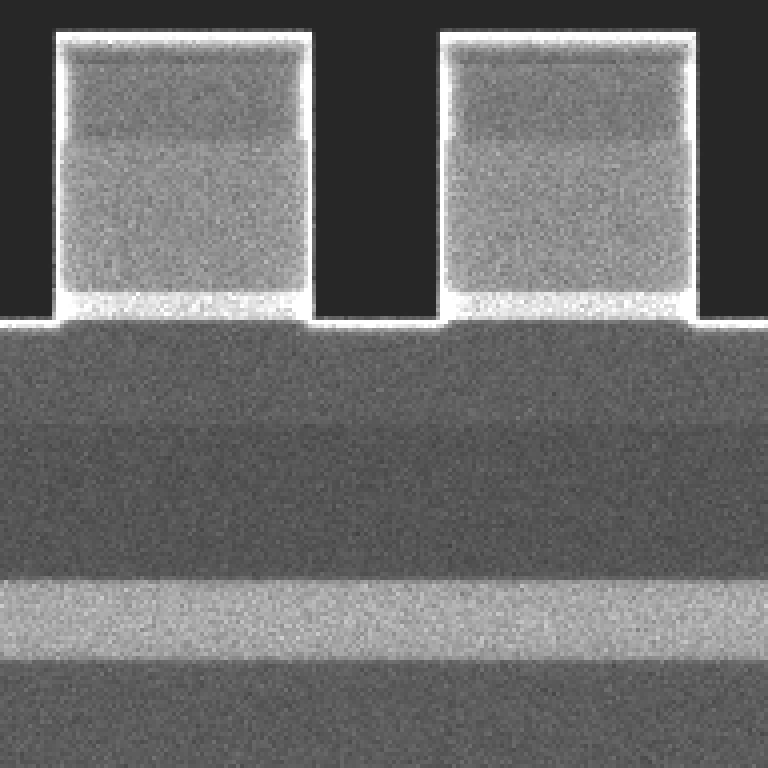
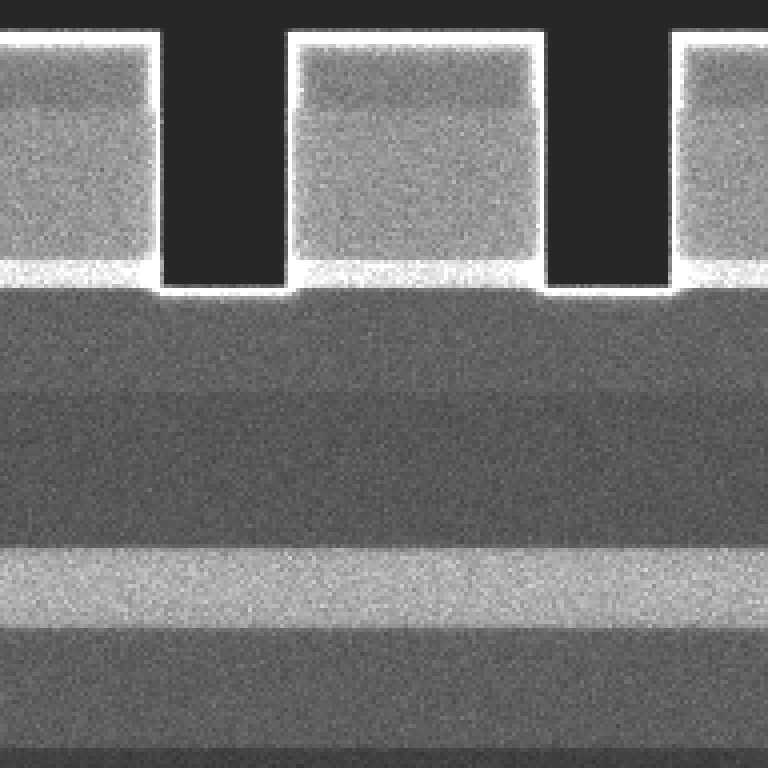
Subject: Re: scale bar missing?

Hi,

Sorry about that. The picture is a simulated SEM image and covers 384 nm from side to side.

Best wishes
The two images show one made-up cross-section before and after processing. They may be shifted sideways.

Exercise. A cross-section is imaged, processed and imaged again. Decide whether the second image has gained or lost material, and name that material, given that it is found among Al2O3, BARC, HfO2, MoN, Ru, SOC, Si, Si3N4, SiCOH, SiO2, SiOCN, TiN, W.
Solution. removed: SOC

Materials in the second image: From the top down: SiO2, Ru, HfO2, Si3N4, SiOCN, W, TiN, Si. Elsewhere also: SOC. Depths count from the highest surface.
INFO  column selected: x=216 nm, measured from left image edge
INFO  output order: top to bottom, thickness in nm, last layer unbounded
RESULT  SiO2 38, Ru 76, HfO2 14, Si3N4 52, SiOCN 78, W 40, TiN 60, Si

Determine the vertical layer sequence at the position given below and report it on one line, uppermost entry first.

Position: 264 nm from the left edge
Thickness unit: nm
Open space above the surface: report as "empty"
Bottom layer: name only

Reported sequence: SiO2 38, Ru 76, HfO2 14, Si3N4 52, SiOCN 78, W 40, TiN 60, Si